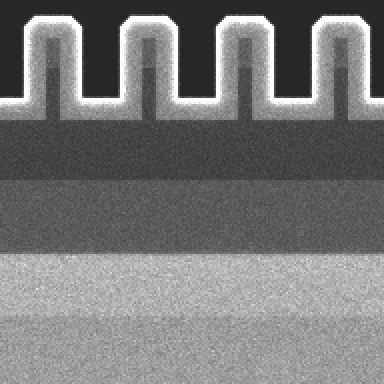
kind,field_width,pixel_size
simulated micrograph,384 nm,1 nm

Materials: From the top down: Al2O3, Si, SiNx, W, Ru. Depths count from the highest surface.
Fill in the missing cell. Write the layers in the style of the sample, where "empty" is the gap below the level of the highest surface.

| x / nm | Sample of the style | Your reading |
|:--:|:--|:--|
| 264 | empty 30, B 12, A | empty 2, Al2O3 102, Si 60, SiNx 74, W 62, Ru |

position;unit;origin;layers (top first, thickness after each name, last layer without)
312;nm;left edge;empty 10, Al2O3 94, Si 60, SiNx 74, W 62, Ru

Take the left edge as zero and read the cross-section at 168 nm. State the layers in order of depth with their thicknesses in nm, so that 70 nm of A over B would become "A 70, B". empty 2, Al2O3 102, Si 60, SiNx 74, W 62, Ru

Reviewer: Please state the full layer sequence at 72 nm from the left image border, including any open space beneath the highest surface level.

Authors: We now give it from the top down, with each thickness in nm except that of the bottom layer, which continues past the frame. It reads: empty 2, Al2O3 102, Si 60, SiNx 74, W 62, Ru